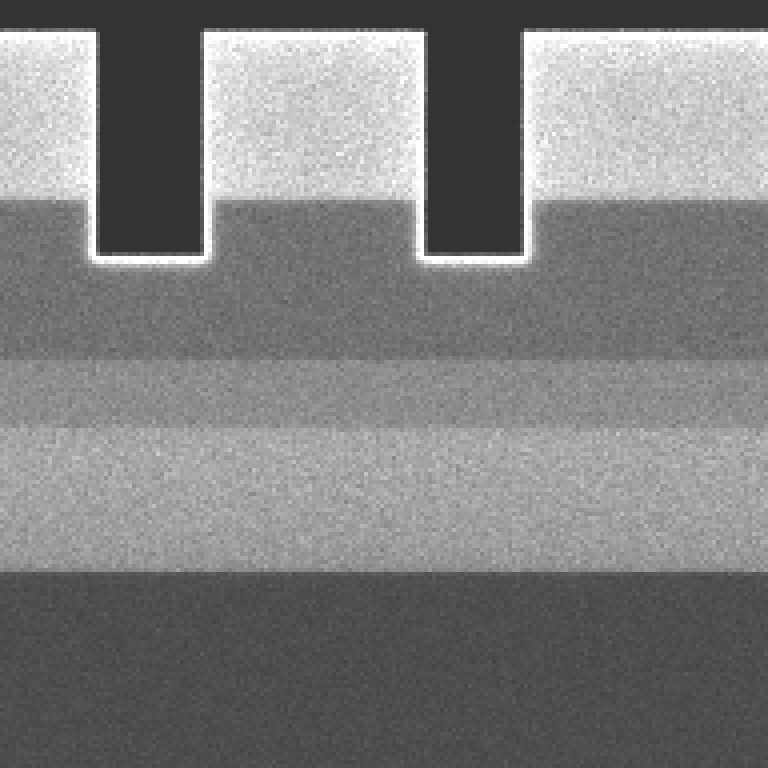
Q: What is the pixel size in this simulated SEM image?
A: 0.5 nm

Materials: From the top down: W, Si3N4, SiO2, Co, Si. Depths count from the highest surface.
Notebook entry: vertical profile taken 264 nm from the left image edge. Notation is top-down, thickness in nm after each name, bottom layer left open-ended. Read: W 84, Si3N4 80, SiO2 34, Co 72, Si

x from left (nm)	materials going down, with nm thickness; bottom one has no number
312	W 84, Si3N4 80, SiO2 34, Co 72, Si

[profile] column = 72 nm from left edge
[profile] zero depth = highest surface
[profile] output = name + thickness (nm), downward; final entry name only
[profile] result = empty 112, Si3N4 52, SiO2 34, Co 72, Si